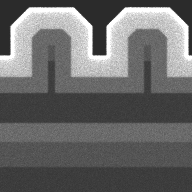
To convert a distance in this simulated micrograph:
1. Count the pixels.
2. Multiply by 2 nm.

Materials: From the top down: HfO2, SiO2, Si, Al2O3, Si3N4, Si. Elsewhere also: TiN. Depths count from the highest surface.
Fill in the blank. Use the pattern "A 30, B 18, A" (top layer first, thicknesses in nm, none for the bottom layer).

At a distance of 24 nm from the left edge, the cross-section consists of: empty 34, HfO2 104, SiO2 32, Si 60, Al2O3 38, Si3N4 50, Si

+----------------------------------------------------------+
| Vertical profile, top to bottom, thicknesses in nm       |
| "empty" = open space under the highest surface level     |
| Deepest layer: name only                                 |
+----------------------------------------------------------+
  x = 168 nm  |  empty 22, HfO2 116, SiO2 32, Si 60, Al2O3 38, Si3N4 50, Si